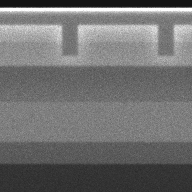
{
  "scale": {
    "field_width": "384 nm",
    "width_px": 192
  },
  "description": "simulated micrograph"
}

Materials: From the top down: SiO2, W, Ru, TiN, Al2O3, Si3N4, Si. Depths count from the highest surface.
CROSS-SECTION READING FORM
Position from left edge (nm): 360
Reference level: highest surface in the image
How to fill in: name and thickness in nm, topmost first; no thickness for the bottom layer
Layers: SiO2 34, W 34, Ru 48, TiN 72, Al2O3 80, Si3N4 44, Si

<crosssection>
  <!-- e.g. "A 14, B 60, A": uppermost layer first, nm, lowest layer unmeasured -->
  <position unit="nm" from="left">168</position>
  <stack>SiO2 34, W 34, Ru 48, TiN 72, Al2O3 80, Si3N4 44, Si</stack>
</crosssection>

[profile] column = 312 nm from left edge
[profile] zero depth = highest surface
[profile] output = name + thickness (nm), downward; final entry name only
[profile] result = SiO2 34, W 34, Ru 48, TiN 72, Al2O3 80, Si3N4 44, Si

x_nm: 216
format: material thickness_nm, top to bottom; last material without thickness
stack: SiO2 34, W 34, Ru 48, TiN 72, Al2O3 80, Si3N4 44, Si